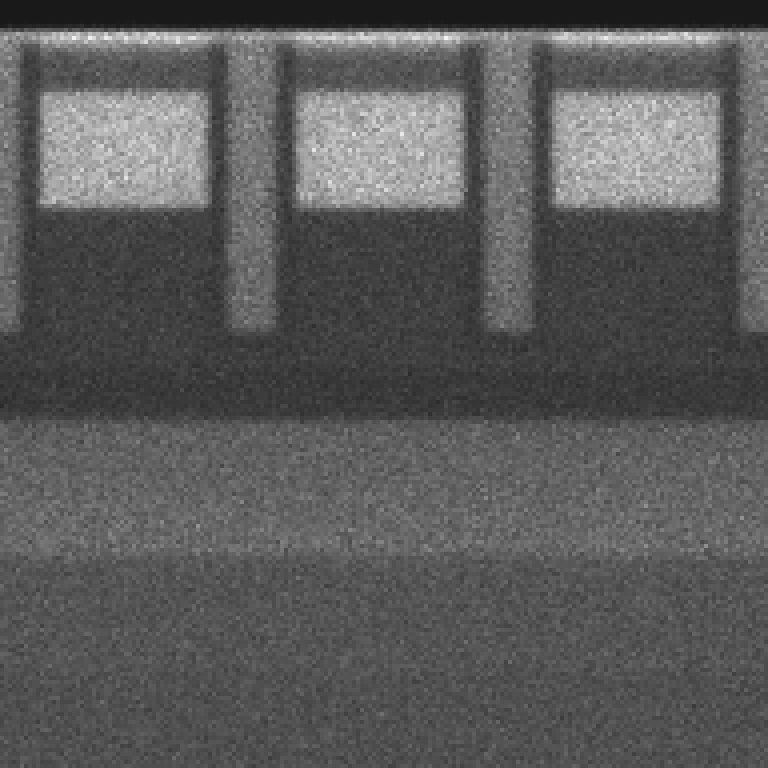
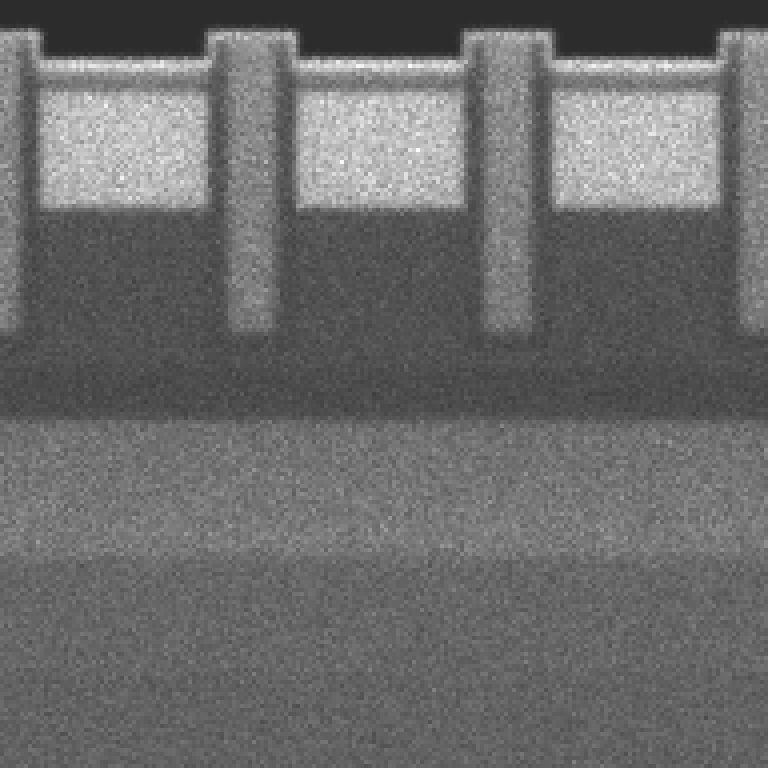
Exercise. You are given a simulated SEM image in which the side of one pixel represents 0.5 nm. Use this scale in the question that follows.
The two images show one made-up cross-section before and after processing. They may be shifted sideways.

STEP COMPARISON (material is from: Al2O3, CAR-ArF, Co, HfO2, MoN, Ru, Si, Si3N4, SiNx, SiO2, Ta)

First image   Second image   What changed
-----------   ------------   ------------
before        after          SiO2, removed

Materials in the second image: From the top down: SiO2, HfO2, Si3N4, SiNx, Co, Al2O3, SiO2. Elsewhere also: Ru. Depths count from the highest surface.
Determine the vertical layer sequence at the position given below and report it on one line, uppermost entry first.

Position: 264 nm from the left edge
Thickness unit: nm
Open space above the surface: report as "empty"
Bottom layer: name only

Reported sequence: Ru 150, SiNx 10, Si3N4 8, SiNx 26, Co 68, Al2O3 58, SiO2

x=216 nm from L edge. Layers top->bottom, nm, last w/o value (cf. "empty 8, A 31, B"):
empty 14, SiO2 16, HfO2 58, Si3N4 80, SiNx 26, Co 68, Al2O3 58, SiO2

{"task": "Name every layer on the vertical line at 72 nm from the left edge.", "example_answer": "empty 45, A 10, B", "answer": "empty 14, SiO2 16, HfO2 58, Si3N4 80, SiNx 26, Co 68, Al2O3 58, SiO2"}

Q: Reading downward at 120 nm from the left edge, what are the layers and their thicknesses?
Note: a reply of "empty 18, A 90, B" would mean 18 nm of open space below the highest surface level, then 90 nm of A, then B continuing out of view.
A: Ru 150, SiNx 10, Si3N4 8, SiNx 26, Co 68, Al2O3 58, SiO2